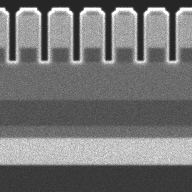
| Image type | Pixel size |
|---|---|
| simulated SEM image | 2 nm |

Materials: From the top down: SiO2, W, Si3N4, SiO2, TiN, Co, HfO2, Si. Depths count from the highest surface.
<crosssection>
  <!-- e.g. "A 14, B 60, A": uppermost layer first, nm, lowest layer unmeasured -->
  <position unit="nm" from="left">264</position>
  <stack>SiO2 14, W 66, Si3N4 28, SiO2 76, TiN 52, Co 24, HfO2 54, Si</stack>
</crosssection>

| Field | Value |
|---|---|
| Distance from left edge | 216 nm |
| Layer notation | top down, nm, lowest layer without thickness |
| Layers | empty 106, SiO2 78, TiN 52, Co 24, HfO2 54, Si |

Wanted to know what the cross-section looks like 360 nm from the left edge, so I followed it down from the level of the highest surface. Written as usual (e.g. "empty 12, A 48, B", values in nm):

SiO2 14, W 66, Si3N4 28, SiO2 76, TiN 52, Co 24, HfO2 54, Si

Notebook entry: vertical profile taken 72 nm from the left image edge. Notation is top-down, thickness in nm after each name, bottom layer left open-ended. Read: SiO2 14, W 66, Si3N4 28, SiO2 76, TiN 52, Co 24, HfO2 54, Si